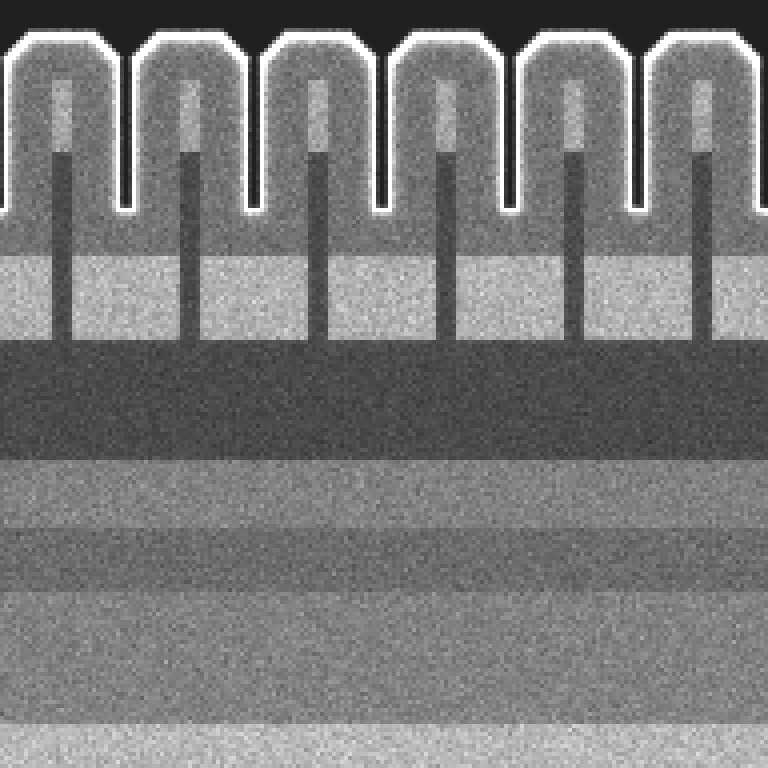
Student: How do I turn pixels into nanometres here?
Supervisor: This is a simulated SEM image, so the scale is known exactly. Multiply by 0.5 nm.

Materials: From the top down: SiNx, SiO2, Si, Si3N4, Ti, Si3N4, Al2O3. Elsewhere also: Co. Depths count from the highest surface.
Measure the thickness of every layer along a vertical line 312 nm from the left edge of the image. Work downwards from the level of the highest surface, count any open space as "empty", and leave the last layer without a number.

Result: empty 10, SiNx 102, SiO2 42, Si 60, Si3N4 34, Ti 32, Si3N4 66, Al2O3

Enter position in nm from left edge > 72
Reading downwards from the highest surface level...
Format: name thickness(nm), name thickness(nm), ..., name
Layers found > empty 6, SiNx 106, SiO2 42, Si 60, Si3N4 34, Ti 32, Si3N4 66, Al2O3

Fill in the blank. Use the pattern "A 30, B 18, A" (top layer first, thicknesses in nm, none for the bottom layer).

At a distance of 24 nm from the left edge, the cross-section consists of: SiNx 112, SiO2 42, Si 60, Si3N4 34, Ti 32, Si3N4 66, Al2O3